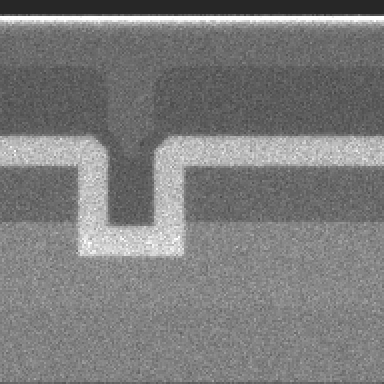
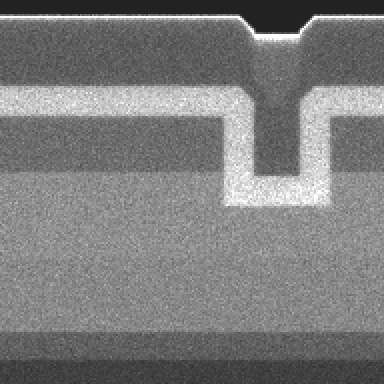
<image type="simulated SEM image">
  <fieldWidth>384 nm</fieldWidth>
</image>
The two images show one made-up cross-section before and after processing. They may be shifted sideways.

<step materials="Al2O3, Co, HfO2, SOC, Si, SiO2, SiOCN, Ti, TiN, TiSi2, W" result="removed SOC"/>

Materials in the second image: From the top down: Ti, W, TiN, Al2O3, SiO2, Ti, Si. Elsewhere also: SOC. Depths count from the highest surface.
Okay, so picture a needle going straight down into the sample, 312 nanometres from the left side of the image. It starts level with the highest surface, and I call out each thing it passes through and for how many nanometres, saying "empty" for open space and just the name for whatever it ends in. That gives empty 2, Ti 70, W 118, Al2O3 52, SiO2 74, Ti 28, Si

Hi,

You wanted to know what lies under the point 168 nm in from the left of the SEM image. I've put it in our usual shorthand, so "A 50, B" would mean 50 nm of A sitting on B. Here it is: Ti 70, W 30, TiN 56, Al2O3 86, SiO2 74, Ti 28, Si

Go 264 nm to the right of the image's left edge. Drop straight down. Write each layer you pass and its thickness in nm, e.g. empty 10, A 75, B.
empty 18, SOC 56, Ti 86, W 30, Al2O3 52, SiO2 74, Ti 28, Si